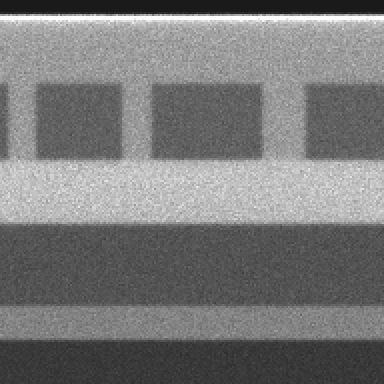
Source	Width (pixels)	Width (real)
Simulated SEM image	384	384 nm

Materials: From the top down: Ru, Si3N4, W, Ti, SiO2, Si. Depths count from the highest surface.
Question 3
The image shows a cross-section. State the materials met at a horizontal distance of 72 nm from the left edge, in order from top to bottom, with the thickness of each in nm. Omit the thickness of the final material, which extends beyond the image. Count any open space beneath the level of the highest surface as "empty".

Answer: Ru 68, Si3N4 76, W 64, Ti 82, SiO2 34, Si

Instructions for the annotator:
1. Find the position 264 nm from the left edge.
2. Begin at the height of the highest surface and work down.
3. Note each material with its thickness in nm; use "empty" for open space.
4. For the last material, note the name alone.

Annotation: Ru 144, W 64, Ti 82, SiO2 34, Si